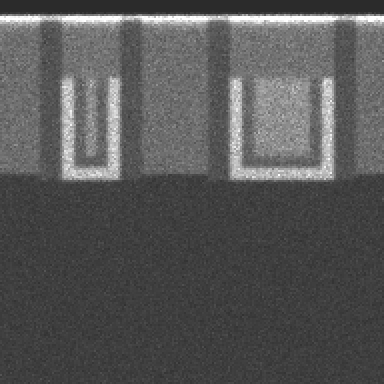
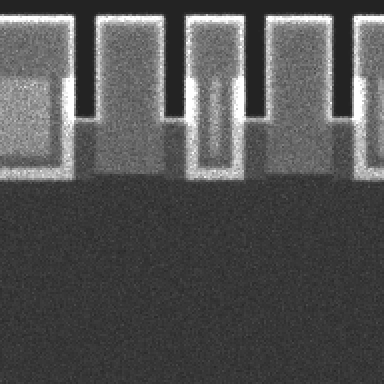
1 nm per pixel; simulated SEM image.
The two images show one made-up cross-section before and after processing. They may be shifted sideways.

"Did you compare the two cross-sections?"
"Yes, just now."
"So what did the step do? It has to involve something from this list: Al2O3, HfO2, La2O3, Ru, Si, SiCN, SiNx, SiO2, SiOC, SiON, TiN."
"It removed SiNx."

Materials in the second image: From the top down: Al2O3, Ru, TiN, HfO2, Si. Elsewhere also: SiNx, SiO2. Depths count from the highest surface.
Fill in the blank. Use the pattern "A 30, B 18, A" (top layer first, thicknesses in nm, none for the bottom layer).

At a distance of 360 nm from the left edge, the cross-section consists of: Al2O3 62, HfO2 102, Si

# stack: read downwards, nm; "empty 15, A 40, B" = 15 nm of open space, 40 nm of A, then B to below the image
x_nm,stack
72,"Al2O3 62, HfO2 102, Si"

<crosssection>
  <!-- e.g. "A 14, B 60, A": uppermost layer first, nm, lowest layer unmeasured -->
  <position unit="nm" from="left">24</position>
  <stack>Al2O3 62, Ru 78, TiN 12, HfO2 12, Si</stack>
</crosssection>